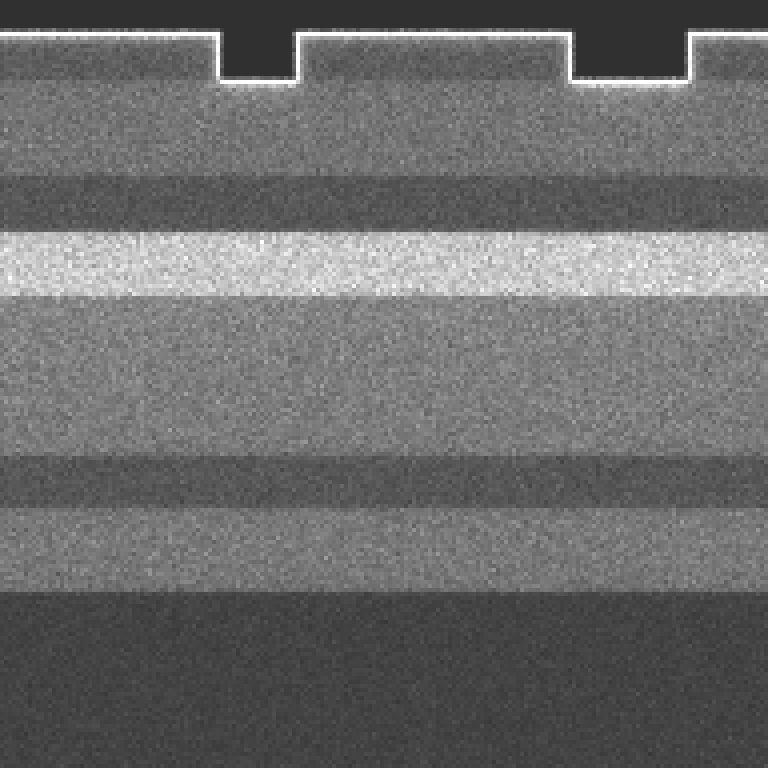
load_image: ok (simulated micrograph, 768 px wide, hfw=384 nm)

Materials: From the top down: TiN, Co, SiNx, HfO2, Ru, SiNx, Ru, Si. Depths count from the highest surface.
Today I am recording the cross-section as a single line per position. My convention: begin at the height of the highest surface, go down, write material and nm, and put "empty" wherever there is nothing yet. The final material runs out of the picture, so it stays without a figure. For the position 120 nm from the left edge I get empty 24, Co 48, SiNx 28, HfO2 32, Ru 80, SiNx 26, Ru 42, Si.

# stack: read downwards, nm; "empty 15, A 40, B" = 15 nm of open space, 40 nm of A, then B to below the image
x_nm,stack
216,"TiN 24, Co 48, SiNx 28, HfO2 32, Ru 80, SiNx 26, Ru 42, Si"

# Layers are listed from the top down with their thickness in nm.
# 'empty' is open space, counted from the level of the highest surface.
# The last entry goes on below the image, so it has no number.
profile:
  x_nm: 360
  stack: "TiN 24, Co 48, SiNx 28, HfO2 32, Ru 80, SiNx 26, Ru 42, Si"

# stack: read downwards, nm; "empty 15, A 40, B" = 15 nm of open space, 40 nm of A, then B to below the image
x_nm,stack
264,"TiN 24, Co 48, SiNx 28, HfO2 32, Ru 80, SiNx 26, Ru 42, Si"